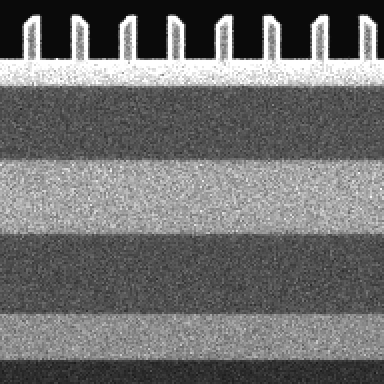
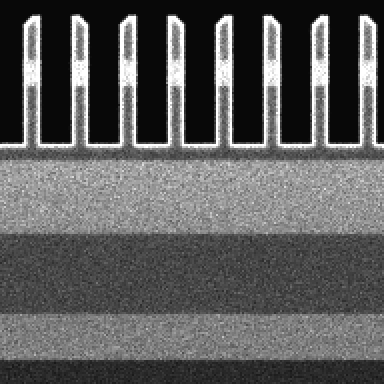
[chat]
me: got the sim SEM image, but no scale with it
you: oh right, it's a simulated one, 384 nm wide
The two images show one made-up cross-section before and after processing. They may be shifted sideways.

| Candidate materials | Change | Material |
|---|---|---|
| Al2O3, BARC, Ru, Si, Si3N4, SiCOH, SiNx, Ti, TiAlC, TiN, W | removed | SiNx and W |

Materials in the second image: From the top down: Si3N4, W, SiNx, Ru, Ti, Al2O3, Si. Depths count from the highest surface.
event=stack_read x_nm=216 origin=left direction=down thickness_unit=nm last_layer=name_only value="empty 8, Si3N4 36, W 26, SiNx 74, Ru 74, Ti 80, Al2O3 46, Si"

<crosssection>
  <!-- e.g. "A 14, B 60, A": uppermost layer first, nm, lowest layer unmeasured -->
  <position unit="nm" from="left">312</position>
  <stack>empty 8, Si3N4 36, W 26, SiNx 74, Ru 74, Ti 80, Al2O3 46, Si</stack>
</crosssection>